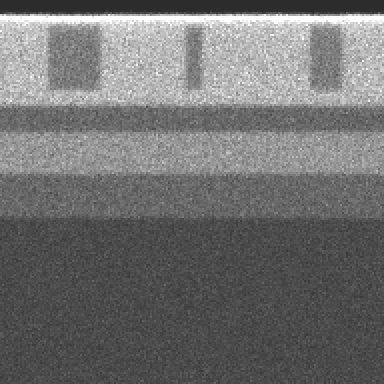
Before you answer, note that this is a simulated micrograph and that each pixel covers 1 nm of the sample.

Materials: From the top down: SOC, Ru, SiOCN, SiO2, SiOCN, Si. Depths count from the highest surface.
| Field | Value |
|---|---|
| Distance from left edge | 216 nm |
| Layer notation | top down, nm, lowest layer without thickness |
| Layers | Ru 90, SiOCN 26, SiO2 42, SiOCN 44, Si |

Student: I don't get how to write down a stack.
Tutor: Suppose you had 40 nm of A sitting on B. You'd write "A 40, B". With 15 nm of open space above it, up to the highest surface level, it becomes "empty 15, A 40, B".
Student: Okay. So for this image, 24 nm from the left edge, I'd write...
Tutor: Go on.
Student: Ru 90, SiOCN 26, SiO2 42, SiOCN 44, Si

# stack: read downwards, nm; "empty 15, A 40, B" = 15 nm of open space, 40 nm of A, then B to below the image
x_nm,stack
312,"SOC 74, Ru 16, SiOCN 26, SiO2 42, SiOCN 44, Si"